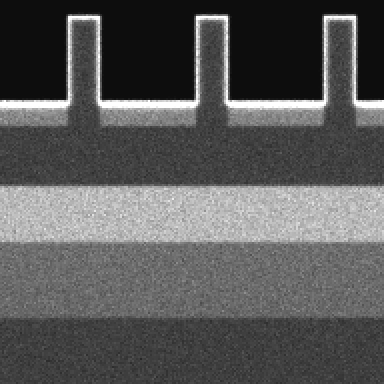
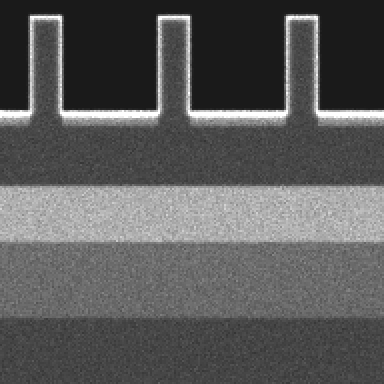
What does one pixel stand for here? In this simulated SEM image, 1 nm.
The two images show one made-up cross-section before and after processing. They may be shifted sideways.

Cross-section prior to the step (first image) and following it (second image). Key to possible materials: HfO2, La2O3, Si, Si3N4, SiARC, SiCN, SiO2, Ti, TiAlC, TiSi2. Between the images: Si3N4 was removed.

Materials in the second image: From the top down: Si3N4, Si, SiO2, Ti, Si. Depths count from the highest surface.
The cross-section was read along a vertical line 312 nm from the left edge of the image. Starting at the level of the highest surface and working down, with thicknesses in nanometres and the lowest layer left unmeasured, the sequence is Si 170, SiO2 56, Ti 76, Si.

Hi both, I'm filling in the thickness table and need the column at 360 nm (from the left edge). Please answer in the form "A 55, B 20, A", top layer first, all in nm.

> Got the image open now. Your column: empty 96, Si3N4 14, Si 60, SiO2 56, Ti 76, Si